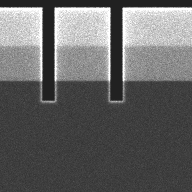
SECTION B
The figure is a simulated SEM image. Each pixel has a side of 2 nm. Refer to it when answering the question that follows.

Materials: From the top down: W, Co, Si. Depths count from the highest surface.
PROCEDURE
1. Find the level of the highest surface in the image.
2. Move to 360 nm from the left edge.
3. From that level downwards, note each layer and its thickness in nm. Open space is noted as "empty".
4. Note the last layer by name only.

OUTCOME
W 76, Co 70, Si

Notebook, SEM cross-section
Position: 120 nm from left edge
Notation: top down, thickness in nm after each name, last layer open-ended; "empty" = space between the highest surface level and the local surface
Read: W 76, Co 70, Si